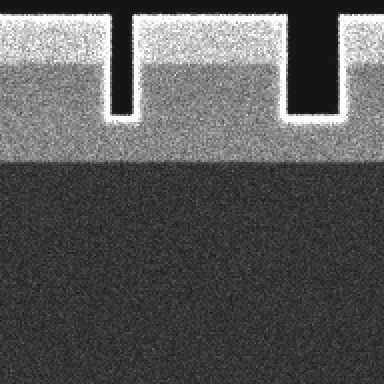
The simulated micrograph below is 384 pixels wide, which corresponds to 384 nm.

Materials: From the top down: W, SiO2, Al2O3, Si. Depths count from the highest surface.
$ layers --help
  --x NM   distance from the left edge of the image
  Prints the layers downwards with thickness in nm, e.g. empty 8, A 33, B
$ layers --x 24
W 48, SiO2 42, Al2O3 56, Si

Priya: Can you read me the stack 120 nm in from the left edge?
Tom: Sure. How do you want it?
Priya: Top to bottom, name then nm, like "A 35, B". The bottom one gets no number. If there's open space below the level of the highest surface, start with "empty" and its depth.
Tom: empty 100, Al2O3 46, Si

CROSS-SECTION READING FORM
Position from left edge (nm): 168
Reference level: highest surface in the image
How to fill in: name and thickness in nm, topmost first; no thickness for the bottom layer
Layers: W 48, SiO2 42, Al2O3 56, Si